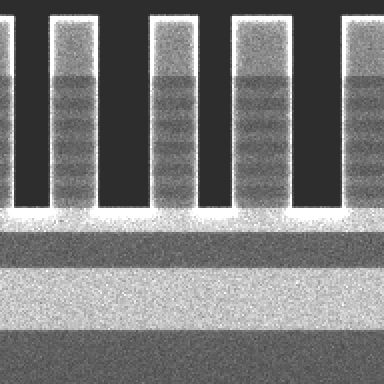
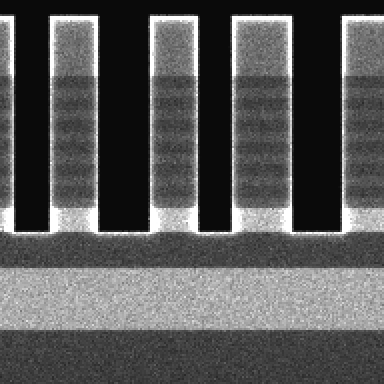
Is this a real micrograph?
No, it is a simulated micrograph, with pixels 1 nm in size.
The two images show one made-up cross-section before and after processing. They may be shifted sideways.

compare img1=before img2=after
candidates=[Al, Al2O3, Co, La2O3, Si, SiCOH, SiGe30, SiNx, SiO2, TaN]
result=removed:Al2O3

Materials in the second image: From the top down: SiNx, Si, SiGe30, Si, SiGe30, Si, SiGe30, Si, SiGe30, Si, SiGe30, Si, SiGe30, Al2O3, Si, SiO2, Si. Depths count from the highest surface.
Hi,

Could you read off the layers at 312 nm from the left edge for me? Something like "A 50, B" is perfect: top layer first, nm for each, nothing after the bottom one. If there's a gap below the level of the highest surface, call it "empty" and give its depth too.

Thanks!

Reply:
empty 216, Si 36, SiO2 62, Si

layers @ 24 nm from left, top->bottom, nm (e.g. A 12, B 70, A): empty 216, Si 36, SiO2 62, Si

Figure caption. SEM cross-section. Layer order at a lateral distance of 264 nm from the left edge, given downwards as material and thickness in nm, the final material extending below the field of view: SiNx 60, Si 12, SiGe30 10, Si 12, SiGe30 10, Si 12, SiGe30 10, Si 12, SiGe30 10, Si 12, SiGe30 10, Si 12, SiGe30 10, Al2O3 24, Si 36, SiO2 62, Si